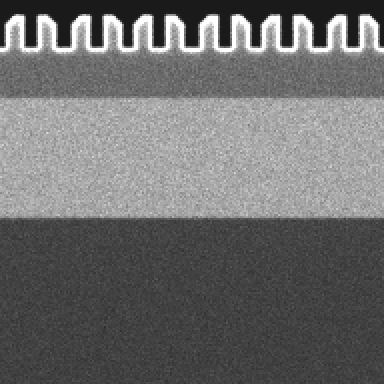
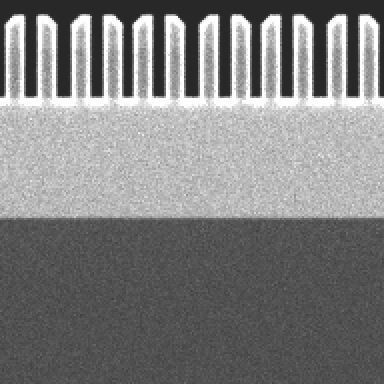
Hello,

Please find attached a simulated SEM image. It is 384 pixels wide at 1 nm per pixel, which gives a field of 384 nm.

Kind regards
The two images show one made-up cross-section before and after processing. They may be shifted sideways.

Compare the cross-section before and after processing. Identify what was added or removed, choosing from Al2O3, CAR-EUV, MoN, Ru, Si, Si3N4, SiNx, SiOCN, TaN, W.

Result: SiNx removed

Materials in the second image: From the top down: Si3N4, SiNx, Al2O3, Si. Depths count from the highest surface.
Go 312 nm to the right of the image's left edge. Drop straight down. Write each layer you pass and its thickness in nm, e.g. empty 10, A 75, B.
empty 82, Al2O3 120, Si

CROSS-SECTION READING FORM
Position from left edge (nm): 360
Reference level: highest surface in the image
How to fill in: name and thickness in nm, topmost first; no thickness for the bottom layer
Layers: Si3N4 32, SiNx 50, Al2O3 120, Si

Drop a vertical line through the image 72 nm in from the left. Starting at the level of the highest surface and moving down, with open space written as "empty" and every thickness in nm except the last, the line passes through empty 8, Si3N4 24, SiNx 50, Al2O3 120, Si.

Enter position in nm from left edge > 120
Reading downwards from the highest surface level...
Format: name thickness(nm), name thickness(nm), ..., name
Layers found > empty 8, Si3N4 24, SiNx 50, Al2O3 120, Si